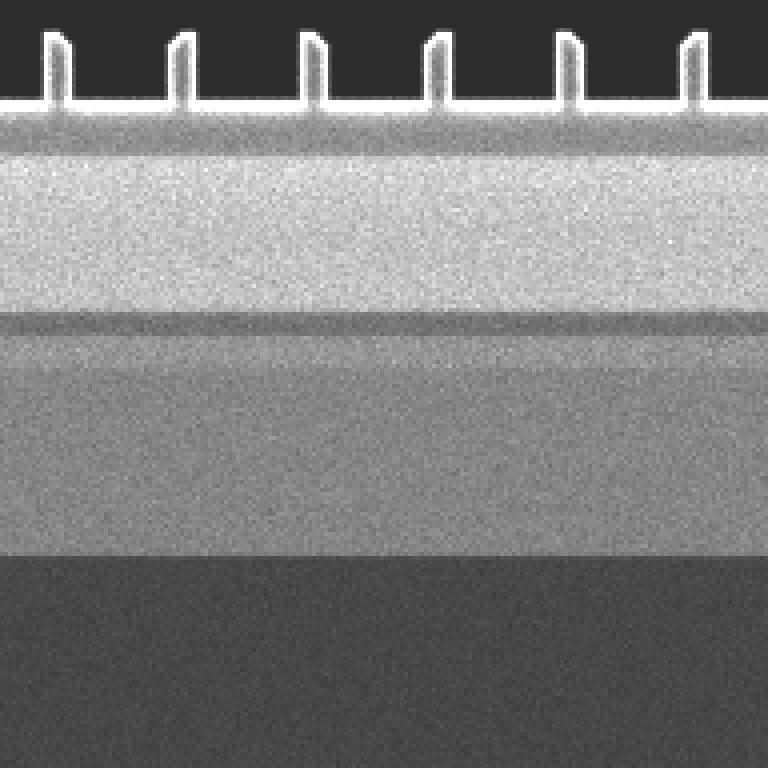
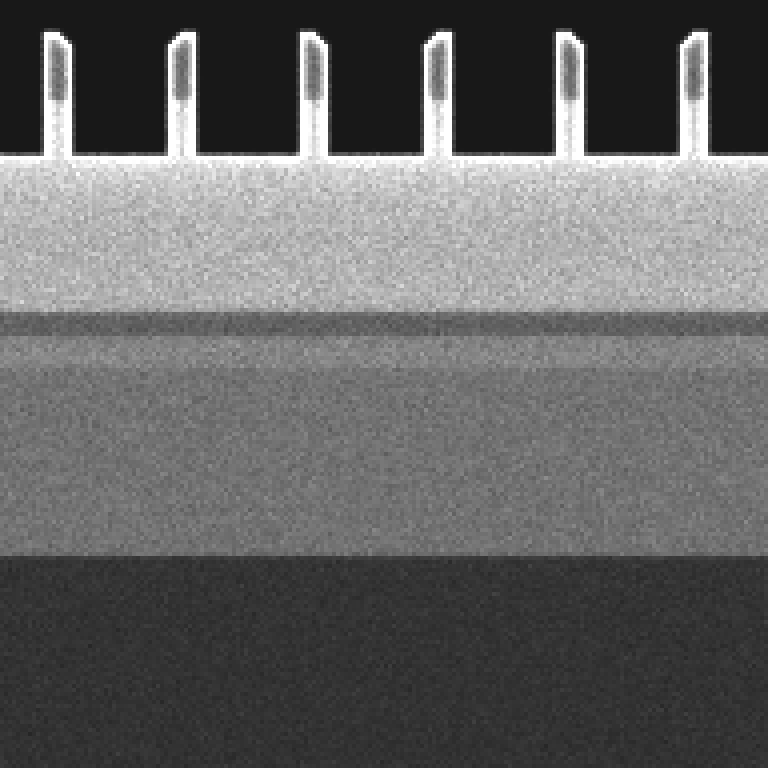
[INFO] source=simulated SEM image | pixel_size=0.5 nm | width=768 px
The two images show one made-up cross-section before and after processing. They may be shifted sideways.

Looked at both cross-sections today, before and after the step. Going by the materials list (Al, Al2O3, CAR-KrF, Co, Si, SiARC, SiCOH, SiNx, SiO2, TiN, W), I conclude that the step removed Al2O3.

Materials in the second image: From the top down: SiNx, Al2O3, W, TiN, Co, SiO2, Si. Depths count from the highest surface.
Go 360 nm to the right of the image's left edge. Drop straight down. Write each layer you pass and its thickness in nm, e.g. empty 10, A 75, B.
empty 62, W 78, TiN 12, Co 16, SiO2 94, Si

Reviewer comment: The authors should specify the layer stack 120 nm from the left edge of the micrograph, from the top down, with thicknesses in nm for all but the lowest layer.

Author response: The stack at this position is empty 62, W 78, TiN 12, Co 16, SiO2 94, Si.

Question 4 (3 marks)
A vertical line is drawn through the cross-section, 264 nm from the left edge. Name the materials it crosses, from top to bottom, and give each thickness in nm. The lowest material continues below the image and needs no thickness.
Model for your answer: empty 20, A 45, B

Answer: empty 62, W 78, TiN 12, Co 16, SiO2 94, Si